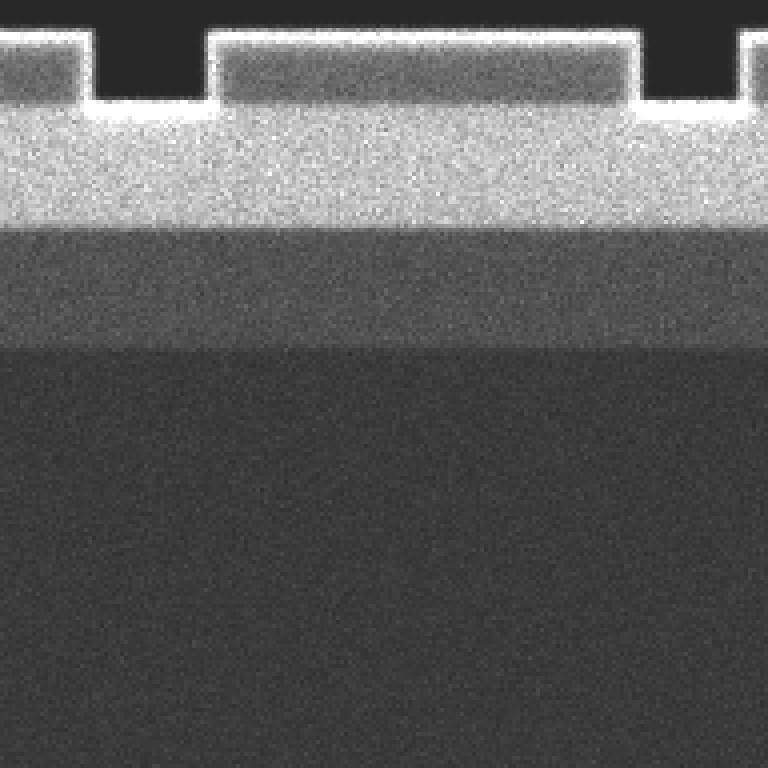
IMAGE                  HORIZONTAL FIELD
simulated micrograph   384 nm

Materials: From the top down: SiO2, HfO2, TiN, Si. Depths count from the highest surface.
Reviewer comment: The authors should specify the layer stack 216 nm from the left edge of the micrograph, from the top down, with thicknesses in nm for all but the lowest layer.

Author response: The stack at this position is SiO2 36, HfO2 62, TiN 60, Si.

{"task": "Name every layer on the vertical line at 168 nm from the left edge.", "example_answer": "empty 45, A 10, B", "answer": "SiO2 36, HfO2 62, TiN 60, Si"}